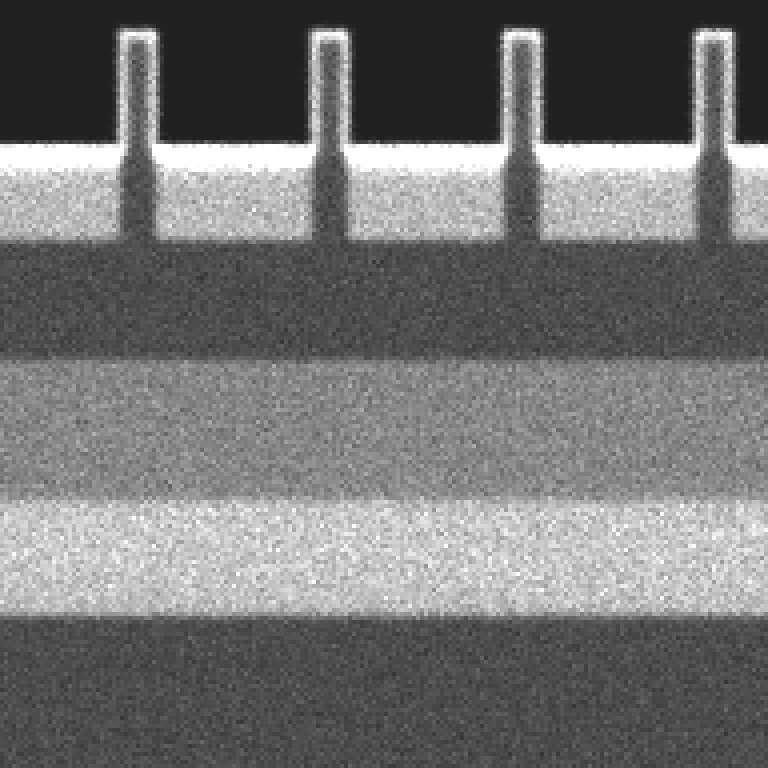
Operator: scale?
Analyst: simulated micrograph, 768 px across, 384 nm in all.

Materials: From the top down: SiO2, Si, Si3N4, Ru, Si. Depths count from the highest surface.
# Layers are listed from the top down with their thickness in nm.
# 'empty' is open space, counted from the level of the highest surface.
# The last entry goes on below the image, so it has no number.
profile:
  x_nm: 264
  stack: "Si 164, Si3N4 70, Ru 58, Si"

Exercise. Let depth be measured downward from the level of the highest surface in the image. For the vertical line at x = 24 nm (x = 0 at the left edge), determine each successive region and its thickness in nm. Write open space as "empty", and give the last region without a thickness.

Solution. empty 58, SiO2 46, Si 60, Si3N4 70, Ru 58, Si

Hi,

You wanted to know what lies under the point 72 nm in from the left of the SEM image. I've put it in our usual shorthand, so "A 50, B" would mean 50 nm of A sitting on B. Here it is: Si 164, Si3N4 70, Ru 58, Si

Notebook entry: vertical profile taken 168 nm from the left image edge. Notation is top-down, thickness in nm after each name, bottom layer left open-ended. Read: Si 164, Si3N4 70, Ru 58, Si